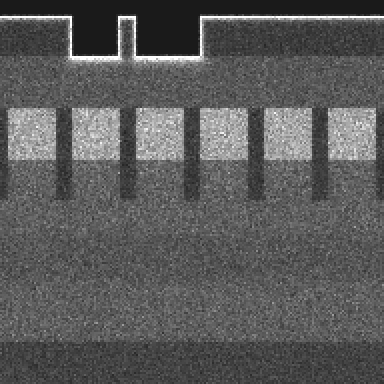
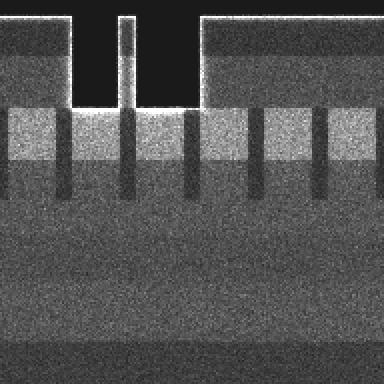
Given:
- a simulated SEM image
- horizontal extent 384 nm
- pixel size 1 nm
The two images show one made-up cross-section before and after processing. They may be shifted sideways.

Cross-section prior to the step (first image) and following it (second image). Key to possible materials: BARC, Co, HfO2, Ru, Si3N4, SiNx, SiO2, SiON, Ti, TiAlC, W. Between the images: SiO2 was removed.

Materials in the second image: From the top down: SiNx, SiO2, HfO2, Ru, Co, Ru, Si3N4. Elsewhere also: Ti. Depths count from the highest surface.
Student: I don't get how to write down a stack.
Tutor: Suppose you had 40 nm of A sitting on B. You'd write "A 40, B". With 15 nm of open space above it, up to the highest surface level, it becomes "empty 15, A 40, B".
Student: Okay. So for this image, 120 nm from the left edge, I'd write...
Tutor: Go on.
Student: SiNx 40, SiO2 52, Ti 92, Ru 36, Co 46, Ru 60, Si3N4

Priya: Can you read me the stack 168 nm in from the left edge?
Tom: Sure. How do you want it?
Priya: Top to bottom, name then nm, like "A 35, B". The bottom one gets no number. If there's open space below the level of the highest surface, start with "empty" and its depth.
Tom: empty 92, HfO2 52, Ru 76, Co 46, Ru 60, Si3N4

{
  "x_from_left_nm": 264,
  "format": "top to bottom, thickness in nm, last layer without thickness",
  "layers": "SiNx 40, SiO2 52, HfO2 52, Ru 76, Co 46, Ru 60, Si3N4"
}